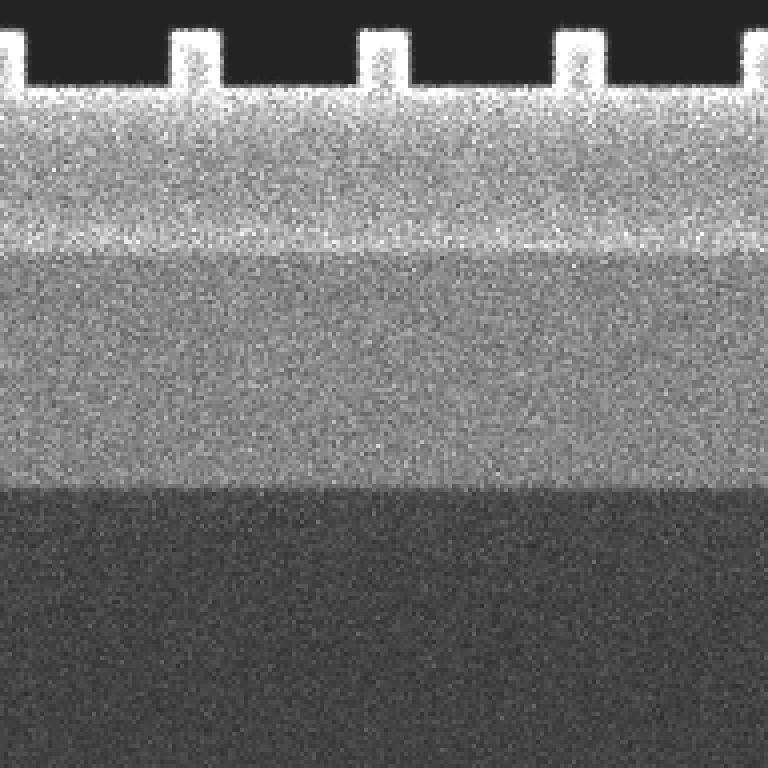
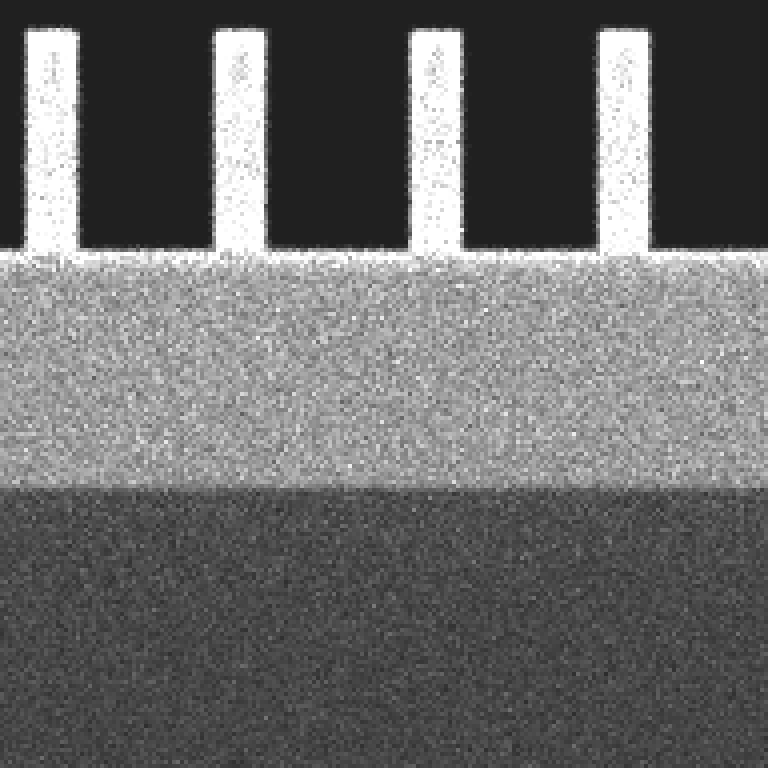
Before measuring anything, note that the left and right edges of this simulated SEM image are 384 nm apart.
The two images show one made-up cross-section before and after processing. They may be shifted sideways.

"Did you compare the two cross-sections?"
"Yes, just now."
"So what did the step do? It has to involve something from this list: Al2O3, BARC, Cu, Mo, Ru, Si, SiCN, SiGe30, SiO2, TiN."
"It removed Ru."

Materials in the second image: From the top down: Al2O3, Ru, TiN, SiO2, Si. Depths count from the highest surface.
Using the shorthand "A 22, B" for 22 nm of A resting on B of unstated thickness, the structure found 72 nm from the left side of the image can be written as empty 110, TiN 10, SiO2 108, Si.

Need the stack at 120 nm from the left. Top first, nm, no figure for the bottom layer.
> Al2O3 28, Ru 82, TiN 10, SiO2 108, Si